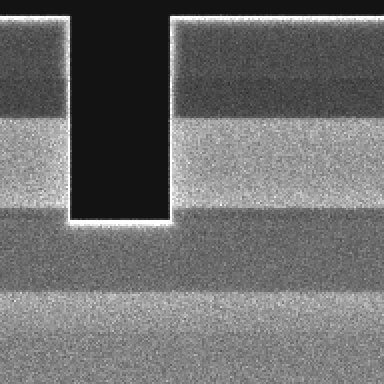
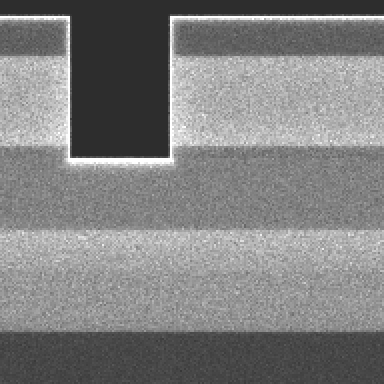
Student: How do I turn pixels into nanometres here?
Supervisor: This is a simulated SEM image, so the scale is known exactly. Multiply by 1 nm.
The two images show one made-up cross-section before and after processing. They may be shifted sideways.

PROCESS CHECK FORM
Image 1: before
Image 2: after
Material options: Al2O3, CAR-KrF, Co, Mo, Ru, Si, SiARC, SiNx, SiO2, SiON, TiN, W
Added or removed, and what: removed, SiARC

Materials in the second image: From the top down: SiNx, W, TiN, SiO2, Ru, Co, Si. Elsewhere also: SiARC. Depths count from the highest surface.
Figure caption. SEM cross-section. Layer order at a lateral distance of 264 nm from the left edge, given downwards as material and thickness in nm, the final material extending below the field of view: SiNx 40, W 90, TiN 12, SiO2 72, Ru 40, Co 62, Si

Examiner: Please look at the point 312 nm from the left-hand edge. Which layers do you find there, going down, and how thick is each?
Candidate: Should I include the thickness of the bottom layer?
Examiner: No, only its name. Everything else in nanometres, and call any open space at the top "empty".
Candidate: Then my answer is SiNx 40, W 90, TiN 12, SiO2 72, Ru 40, Co 62, Si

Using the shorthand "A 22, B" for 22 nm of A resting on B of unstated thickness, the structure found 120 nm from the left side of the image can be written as empty 142, SiO2 72, Ru 40, Co 62, Si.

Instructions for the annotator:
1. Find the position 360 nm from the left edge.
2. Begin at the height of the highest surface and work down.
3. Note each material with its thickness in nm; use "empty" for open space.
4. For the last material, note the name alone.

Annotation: SiNx 40, W 90, TiN 12, SiO2 72, Ru 40, Co 62, Si